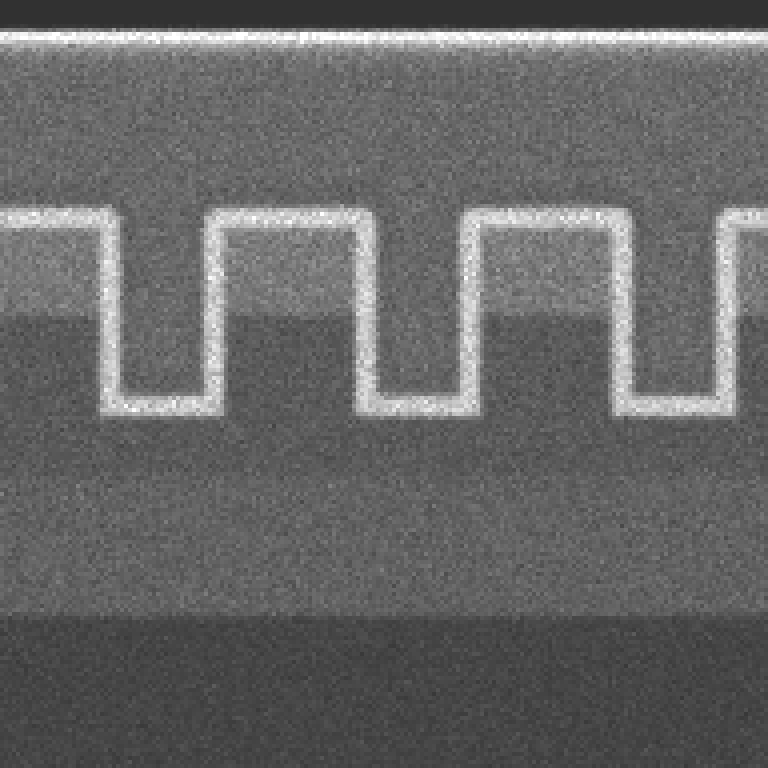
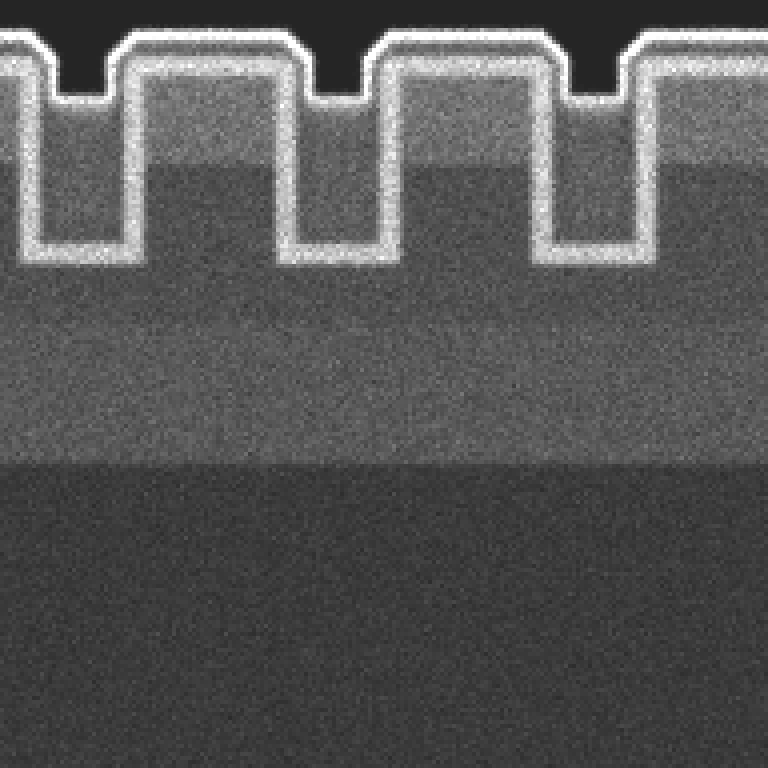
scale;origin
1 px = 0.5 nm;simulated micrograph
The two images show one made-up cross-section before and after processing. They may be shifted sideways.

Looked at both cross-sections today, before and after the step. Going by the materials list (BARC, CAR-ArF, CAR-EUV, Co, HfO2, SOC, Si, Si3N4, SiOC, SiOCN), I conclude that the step removed SOC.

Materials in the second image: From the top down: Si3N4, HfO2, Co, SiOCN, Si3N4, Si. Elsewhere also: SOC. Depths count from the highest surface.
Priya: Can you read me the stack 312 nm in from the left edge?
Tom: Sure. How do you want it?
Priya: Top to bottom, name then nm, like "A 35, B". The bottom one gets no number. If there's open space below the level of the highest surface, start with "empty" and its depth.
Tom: empty 10, Si3N4 96, HfO2 10, SiOCN 30, Si3N4 70, Si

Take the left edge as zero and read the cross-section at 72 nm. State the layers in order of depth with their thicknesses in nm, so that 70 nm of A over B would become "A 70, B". Si3N4 12, HfO2 10, Co 44, SiOCN 80, Si3N4 70, Si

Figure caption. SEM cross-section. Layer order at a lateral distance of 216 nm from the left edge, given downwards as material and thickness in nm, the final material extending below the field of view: Si3N4 12, HfO2 10, Co 44, SiOCN 80, Si3N4 70, Si